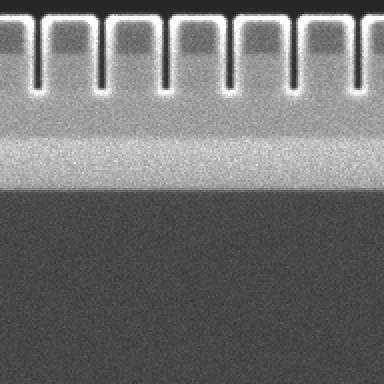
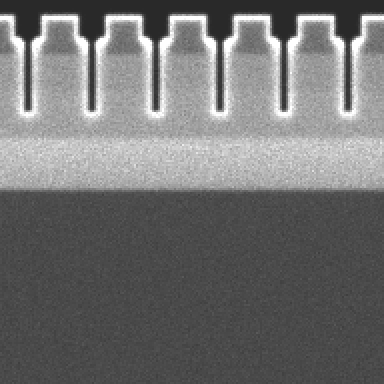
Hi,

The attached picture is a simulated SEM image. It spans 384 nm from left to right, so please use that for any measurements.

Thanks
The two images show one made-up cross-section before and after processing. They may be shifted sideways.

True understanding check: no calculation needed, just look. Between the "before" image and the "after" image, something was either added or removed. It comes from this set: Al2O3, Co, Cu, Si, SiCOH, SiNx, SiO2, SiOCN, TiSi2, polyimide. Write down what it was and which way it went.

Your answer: Al2O3 (removed)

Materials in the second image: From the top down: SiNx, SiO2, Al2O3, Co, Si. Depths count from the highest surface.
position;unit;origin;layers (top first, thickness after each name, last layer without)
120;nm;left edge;SiNx 38, SiO2 36, Al2O3 48, Co 52, Si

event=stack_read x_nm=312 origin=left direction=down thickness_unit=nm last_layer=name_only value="SiNx 38, SiO2 36, Al2O3 48, Co 52, Si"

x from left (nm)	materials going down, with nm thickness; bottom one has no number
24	empty 96, Al2O3 26, Co 52, Si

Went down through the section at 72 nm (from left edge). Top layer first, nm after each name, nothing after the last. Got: SiNx 38, SiO2 36, Al2O3 48, Co 52, Si